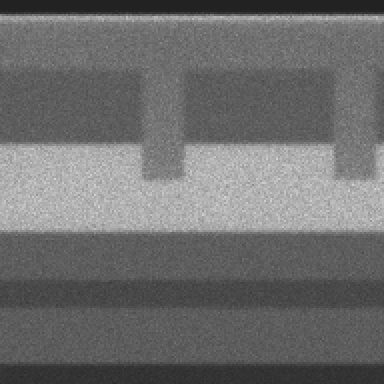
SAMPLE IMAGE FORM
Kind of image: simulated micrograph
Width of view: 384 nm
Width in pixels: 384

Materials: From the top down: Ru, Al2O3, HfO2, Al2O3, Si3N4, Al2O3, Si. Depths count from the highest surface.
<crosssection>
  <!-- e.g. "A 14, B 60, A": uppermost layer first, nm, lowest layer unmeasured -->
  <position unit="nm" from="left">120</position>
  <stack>Ru 54, Al2O3 74, HfO2 88, Al2O3 48, Si3N4 28, Al2O3 56, Si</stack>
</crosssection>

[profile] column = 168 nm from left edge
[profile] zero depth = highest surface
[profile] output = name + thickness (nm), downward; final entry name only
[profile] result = Ru 164, HfO2 52, Al2O3 48, Si3N4 28, Al2O3 56, Si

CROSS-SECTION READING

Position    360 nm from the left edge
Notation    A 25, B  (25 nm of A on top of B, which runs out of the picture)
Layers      Ru 164, HfO2 52, Al2O3 48, Si3N4 28, Al2O3 56, Si